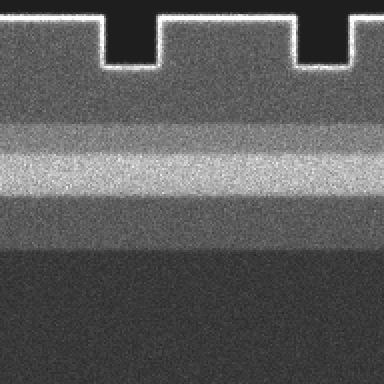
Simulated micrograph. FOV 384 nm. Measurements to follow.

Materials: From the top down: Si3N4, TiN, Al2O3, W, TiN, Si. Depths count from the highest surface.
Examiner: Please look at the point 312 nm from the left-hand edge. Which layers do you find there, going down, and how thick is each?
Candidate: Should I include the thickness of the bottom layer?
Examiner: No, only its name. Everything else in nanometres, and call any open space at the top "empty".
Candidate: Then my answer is empty 50, TiN 58, Al2O3 30, W 42, TiN 54, Si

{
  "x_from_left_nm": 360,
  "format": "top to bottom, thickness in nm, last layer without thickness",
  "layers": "Si3N4 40, TiN 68, Al2O3 30, W 42, TiN 54, Si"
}